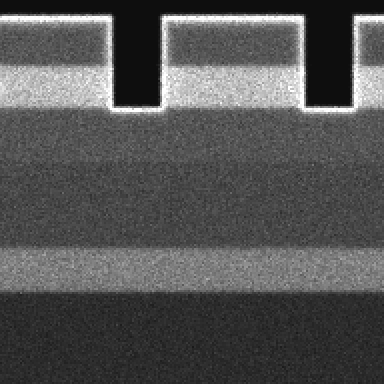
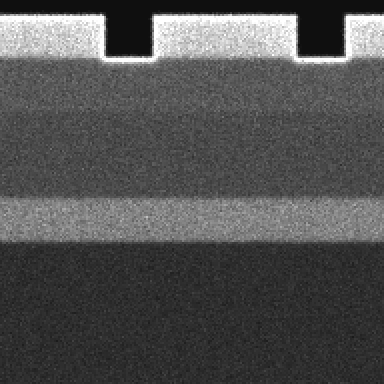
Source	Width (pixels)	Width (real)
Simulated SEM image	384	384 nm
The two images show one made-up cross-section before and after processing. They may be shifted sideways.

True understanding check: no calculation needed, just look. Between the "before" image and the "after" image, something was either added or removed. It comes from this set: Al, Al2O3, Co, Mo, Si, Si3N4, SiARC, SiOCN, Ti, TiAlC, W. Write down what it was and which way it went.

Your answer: SiARC (removed)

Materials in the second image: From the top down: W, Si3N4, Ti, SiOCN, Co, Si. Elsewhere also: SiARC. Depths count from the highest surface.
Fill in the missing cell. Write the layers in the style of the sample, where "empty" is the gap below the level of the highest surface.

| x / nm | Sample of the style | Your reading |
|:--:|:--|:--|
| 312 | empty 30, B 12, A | empty 42, Si3N4 54, Ti 20, SiOCN 66, Co 44, Si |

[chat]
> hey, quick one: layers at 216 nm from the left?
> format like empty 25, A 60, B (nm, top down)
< W 42, Si3N4 54, Ti 20, SiOCN 66, Co 44, Si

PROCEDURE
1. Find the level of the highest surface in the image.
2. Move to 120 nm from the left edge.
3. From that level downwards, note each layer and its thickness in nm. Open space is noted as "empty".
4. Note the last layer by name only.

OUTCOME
empty 42, Si3N4 54, Ti 20, SiOCN 66, Co 44, Si